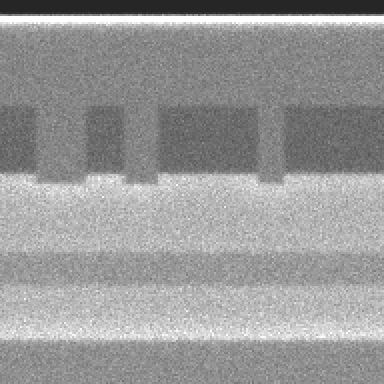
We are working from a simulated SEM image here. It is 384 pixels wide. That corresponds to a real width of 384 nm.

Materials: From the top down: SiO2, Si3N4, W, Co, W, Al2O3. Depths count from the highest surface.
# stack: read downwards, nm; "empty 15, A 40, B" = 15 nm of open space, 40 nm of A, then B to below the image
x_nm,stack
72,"SiO2 168, W 68, Co 34, W 54, Al2O3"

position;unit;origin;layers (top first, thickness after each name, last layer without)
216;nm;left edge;SiO2 90, Si3N4 68, W 78, Co 34, W 54, Al2O3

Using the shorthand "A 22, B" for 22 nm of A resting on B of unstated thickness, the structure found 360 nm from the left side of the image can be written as SiO2 90, Si3N4 68, W 78, Co 34, W 54, Al2O3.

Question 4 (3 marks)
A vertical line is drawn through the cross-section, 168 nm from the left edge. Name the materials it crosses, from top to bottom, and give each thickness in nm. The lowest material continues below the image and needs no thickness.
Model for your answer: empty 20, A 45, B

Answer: SiO2 90, Si3N4 68, W 78, Co 34, W 54, Al2O3